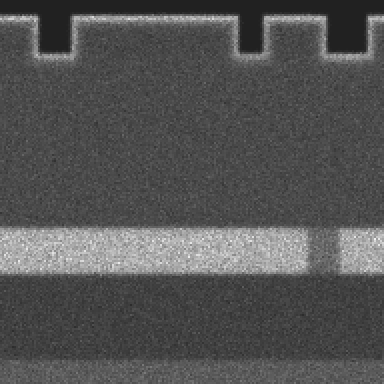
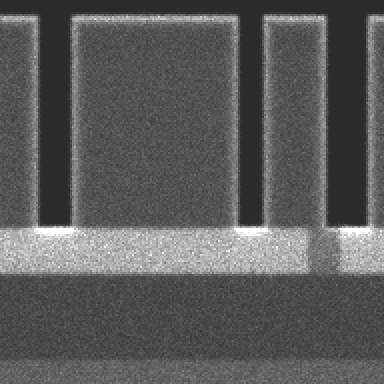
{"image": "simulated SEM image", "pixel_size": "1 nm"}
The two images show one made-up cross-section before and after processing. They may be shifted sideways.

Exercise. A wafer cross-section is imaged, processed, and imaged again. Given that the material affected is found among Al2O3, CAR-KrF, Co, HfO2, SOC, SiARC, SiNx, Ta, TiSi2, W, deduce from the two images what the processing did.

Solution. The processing removed SOC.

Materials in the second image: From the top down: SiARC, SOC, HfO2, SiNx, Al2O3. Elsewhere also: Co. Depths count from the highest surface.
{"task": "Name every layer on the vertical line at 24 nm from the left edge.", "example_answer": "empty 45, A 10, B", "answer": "SiARC 38, SOC 174, HfO2 46, SiNx 86, Al2O3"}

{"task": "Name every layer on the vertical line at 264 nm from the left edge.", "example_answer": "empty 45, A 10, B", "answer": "SiARC 38, SOC 174, HfO2 46, SiNx 86, Al2O3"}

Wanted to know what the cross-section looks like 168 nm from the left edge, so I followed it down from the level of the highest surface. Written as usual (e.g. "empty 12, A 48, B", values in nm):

SiARC 38, SOC 174, HfO2 46, SiNx 86, Al2O3